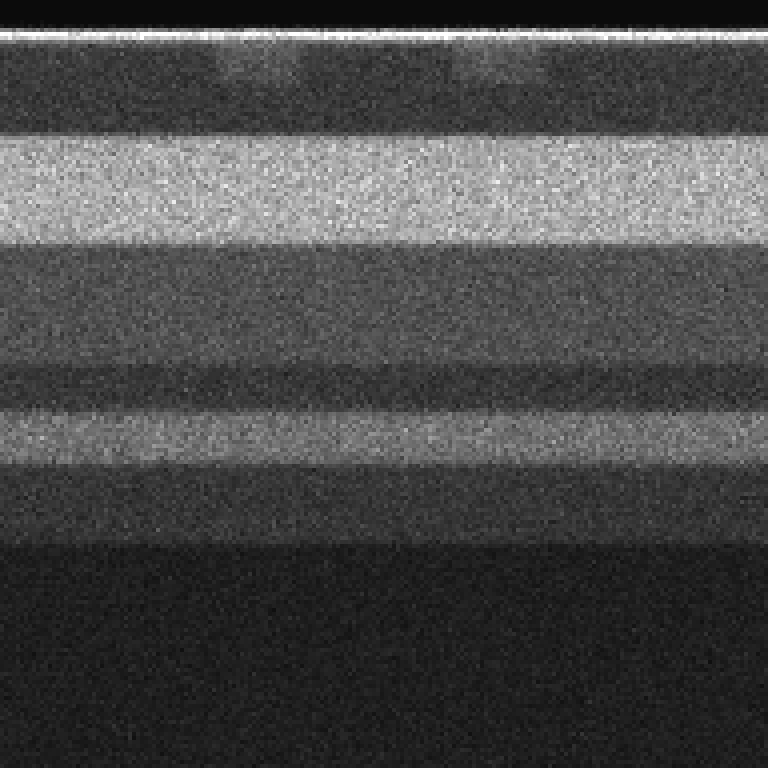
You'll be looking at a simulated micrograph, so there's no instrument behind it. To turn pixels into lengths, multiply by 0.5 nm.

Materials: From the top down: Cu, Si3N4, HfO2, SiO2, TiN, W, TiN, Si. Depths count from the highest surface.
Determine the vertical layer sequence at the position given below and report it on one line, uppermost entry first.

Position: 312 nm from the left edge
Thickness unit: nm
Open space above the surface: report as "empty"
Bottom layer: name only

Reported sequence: Si3N4 52, HfO2 54, SiO2 60, TiN 24, W 26, TiN 40, Si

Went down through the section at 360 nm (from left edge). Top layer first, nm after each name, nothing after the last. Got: Si3N4 52, HfO2 54, SiO2 60, TiN 24, W 26, TiN 40, Si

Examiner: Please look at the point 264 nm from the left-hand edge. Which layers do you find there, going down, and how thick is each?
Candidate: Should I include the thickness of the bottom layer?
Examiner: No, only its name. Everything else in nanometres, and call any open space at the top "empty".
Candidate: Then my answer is Cu 26, Si3N4 26, HfO2 54, SiO2 60, TiN 24, W 26, TiN 40, Si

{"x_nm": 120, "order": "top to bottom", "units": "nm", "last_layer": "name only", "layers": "Cu 26, Si3N4 26, HfO2 54, SiO2 60, TiN 24, W 26, TiN 40, Si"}